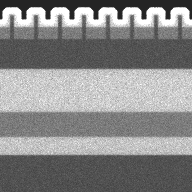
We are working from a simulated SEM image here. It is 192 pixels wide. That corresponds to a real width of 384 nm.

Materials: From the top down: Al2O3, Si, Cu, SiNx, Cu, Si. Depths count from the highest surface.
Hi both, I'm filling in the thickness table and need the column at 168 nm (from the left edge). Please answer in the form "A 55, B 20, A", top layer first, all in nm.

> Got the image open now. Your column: Al2O3 14, Si 108, Cu 86, SiNx 50, Cu 36, Si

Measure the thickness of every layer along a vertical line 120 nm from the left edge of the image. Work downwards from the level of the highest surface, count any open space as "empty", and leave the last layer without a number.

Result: Al2O3 14, Si 108, Cu 86, SiNx 50, Cu 36, Si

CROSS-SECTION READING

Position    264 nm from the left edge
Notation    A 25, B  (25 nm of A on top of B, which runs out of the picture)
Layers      Al2O3 14, Si 108, Cu 86, SiNx 50, Cu 36, Si